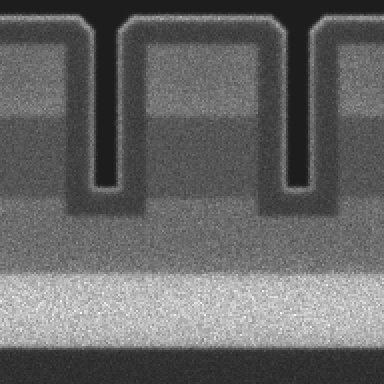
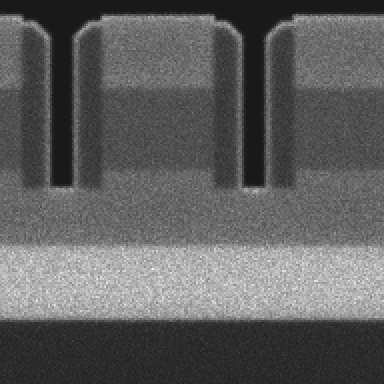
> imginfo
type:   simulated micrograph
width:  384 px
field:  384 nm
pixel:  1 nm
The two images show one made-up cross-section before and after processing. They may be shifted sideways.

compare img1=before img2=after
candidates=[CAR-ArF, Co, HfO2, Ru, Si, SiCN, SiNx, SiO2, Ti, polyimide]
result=removed:SiNx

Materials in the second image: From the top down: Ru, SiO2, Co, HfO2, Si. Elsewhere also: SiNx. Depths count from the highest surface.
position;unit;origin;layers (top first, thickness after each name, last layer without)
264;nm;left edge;empty 172, Co 58, HfO2 74, Si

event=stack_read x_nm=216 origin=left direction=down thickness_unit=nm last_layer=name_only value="empty 6, SiNx 166, Co 58, HfO2 74, Si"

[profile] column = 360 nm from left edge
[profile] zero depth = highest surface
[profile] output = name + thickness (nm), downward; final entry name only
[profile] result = Ru 72, SiO2 82, Co 76, HfO2 74, Si